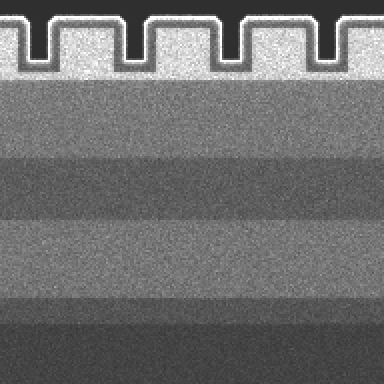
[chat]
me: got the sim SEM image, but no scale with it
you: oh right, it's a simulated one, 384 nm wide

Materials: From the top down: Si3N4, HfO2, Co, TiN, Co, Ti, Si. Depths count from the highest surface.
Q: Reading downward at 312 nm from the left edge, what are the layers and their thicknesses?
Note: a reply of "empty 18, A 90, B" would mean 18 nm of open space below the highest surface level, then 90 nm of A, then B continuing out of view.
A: empty 2, Si3N4 54, HfO2 8, Co 78, TiN 62, Co 78, Ti 26, Si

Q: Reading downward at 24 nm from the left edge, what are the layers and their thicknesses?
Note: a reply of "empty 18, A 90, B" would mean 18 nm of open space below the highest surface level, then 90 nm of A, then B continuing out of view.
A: empty 2, Si3N4 54, HfO2 8, Co 78, TiN 62, Co 78, Ti 26, Si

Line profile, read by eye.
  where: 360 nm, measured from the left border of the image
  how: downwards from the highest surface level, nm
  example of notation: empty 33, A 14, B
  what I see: Si3N4 12, HfO2 52, Co 78, TiN 62, Co 78, Ti 26, Si